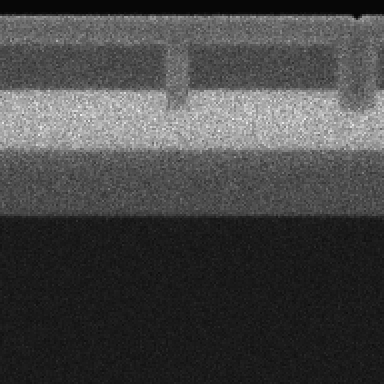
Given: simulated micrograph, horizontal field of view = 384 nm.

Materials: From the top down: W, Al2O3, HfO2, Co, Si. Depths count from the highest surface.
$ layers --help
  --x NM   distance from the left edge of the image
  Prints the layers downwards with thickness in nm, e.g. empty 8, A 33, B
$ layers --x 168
W 94, HfO2 40, Co 66, Si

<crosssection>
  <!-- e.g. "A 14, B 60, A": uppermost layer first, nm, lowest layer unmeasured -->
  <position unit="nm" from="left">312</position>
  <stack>W 28, Al2O3 46, HfO2 60, Co 66, Si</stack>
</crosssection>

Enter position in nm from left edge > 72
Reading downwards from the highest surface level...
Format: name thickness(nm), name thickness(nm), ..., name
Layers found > W 28, Al2O3 46, HfO2 60, Co 66, Si